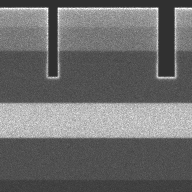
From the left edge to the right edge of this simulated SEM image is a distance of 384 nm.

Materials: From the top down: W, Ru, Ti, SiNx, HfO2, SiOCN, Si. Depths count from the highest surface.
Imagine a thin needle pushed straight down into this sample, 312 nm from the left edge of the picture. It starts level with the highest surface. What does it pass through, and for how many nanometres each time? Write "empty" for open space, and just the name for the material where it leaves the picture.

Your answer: W 38, Ru 48, Ti 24, SiNx 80, HfO2 70, SiOCN 84, Si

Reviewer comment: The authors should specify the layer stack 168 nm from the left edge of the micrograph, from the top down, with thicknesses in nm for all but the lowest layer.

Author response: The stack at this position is W 38, Ru 48, Ti 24, SiNx 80, HfO2 70, SiOCN 84, Si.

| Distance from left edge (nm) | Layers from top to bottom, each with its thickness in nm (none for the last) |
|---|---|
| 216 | W 38, Ru 48, Ti 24, SiNx 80, HfO2 70, SiOCN 84, Si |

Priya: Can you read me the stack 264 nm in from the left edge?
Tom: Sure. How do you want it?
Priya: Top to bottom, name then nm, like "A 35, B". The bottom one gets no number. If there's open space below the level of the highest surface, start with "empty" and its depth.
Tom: W 38, Ru 48, Ti 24, SiNx 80, HfO2 70, SiOCN 84, Si